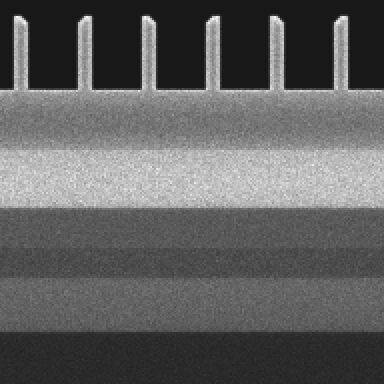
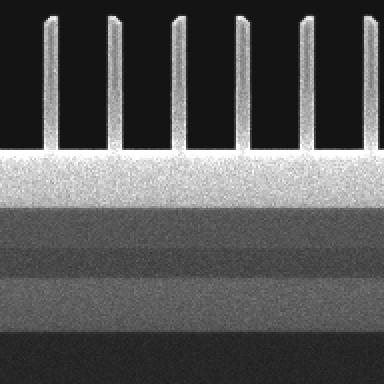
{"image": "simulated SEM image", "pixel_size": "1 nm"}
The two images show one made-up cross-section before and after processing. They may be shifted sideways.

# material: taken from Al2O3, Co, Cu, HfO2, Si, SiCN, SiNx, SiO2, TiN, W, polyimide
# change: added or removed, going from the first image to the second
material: W
change: removed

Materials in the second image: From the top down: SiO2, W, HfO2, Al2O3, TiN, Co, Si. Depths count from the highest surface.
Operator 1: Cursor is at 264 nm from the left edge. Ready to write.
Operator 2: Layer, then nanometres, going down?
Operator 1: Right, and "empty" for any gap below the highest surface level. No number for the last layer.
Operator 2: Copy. empty 134, HfO2 58, Al2O3 40, TiN 30, Co 54, Si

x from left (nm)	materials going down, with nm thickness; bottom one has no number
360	empty 134, HfO2 58, Al2O3 40, TiN 30, Co 54, Si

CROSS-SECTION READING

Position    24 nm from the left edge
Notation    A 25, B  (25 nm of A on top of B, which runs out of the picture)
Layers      empty 134, HfO2 58, Al2O3 40, TiN 30, Co 54, Si